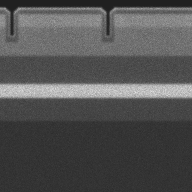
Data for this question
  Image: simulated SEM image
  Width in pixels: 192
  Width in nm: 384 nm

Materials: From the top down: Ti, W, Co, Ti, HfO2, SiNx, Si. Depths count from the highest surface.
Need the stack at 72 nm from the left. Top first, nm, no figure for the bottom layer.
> Ti 12, W 26, Co 58, Ti 56, HfO2 28, SiNx 46, Si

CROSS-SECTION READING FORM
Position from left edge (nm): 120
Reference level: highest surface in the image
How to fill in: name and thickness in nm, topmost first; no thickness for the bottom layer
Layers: Ti 12, W 26, Co 58, Ti 56, HfO2 28, SiNx 46, Si